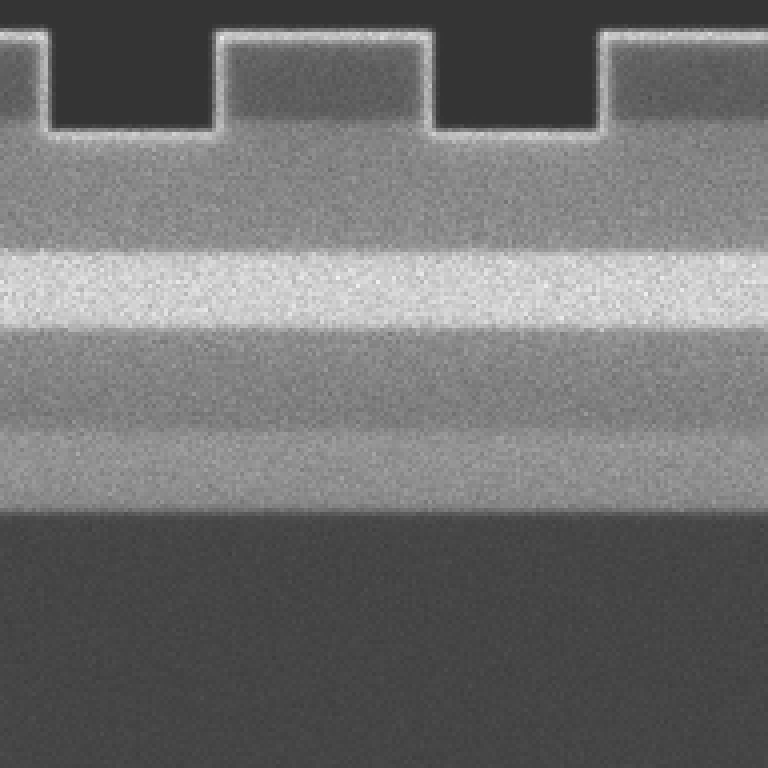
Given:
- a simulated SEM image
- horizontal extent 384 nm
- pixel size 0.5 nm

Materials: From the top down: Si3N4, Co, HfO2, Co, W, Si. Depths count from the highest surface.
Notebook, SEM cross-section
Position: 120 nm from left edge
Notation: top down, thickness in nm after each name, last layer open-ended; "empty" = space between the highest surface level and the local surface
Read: Si3N4 44, Co 66, HfO2 38, Co 52, W 40, Si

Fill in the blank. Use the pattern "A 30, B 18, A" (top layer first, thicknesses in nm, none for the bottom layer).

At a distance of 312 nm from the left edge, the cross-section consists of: Si3N4 44, Co 66, HfO2 38, Co 52, W 40, Si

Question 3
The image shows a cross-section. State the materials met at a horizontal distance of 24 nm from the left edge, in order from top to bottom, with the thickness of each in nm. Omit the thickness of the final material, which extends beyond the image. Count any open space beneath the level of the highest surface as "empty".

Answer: empty 50, Co 60, HfO2 38, Co 52, W 40, Si